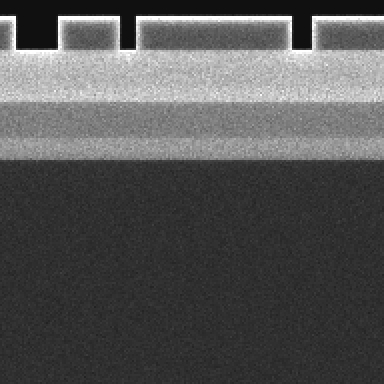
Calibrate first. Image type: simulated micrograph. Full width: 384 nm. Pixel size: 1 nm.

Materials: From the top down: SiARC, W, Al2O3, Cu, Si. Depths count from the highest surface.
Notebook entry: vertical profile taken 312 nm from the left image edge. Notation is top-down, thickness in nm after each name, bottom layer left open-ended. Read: SiARC 34, W 52, Al2O3 36, Cu 22, Si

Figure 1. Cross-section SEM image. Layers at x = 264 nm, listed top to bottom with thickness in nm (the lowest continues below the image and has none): SiARC 34, W 52, Al2O3 36, Cu 22, Si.